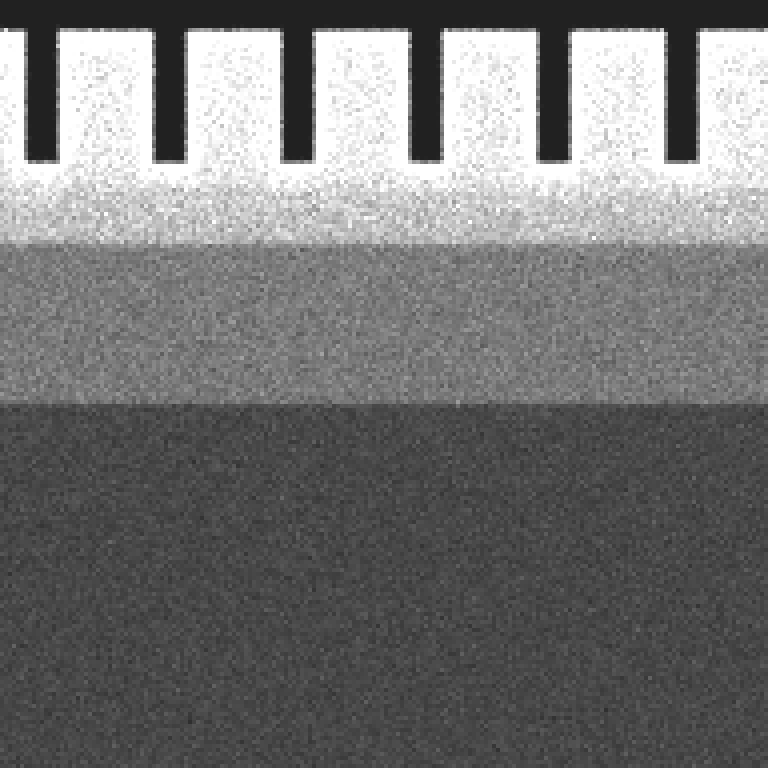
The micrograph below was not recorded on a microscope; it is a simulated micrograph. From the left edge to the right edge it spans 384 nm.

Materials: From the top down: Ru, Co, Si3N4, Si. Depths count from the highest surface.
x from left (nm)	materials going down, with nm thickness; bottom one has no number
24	empty 66, Ru 12, Co 28, Si3N4 80, Si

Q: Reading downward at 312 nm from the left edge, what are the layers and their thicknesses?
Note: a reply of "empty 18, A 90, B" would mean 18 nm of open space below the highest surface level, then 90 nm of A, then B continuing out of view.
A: Ru 78, Co 28, Si3N4 80, Si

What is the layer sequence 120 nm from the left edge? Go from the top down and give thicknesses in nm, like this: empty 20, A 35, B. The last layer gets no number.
Ru 78, Co 28, Si3N4 80, Si